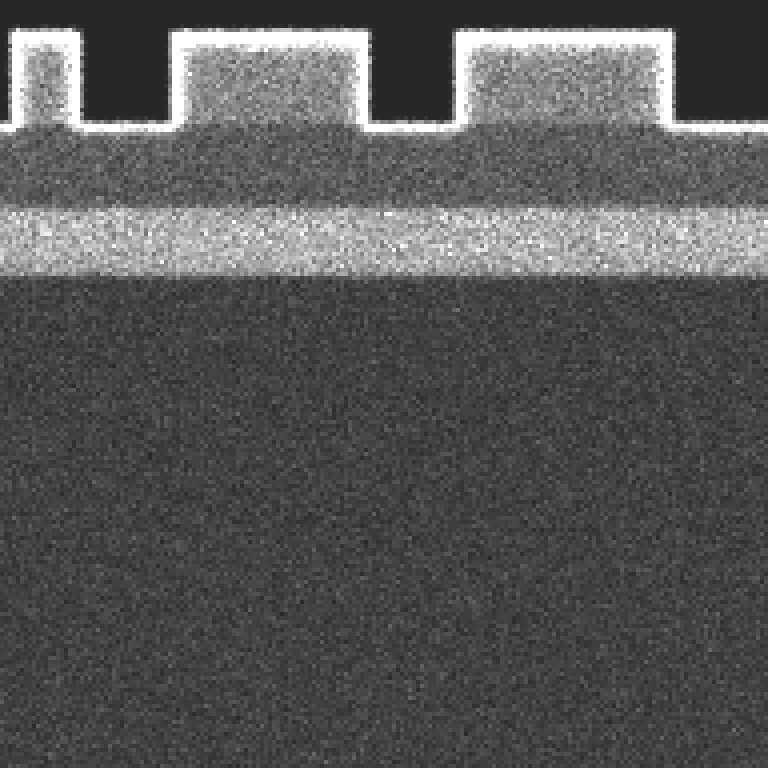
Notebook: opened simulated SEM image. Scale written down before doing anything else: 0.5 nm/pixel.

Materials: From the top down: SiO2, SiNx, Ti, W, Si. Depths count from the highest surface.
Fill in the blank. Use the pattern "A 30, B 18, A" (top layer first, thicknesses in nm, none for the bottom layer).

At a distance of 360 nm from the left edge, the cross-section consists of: empty 46, SiNx 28, Ti 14, W 34, Si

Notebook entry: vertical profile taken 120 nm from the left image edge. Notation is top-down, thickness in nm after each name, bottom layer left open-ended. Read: SiO2 46, SiNx 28, Ti 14, W 34, Si